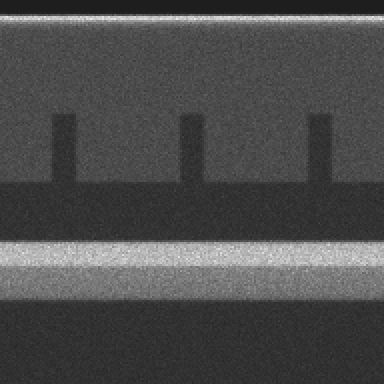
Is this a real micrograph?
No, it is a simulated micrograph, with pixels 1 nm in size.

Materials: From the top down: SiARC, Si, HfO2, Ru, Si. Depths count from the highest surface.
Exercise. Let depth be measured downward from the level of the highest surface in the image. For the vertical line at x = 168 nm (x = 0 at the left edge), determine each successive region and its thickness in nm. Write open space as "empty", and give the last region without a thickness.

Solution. SiARC 166, Si 60, HfO2 24, Ru 34, Si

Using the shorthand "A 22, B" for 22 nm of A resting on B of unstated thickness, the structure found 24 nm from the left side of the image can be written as SiARC 166, Si 60, HfO2 24, Ru 34, Si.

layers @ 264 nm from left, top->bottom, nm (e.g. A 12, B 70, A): SiARC 166, Si 60, HfO2 24, Ru 34, Si